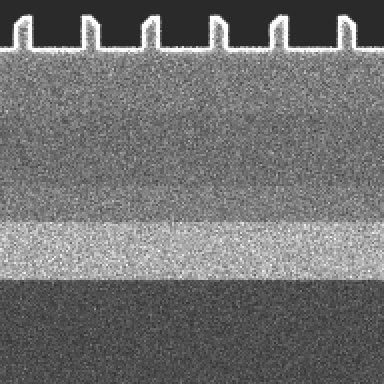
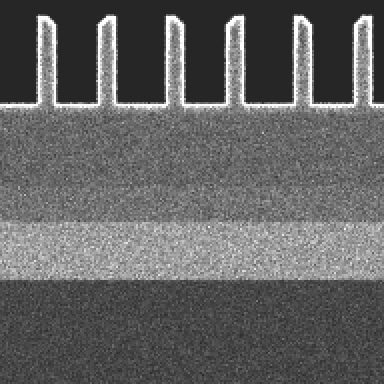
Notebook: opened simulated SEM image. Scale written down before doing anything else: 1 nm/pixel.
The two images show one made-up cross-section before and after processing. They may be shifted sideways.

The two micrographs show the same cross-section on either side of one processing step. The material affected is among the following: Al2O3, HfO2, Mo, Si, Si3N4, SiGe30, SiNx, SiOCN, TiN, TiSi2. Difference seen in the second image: TiN removed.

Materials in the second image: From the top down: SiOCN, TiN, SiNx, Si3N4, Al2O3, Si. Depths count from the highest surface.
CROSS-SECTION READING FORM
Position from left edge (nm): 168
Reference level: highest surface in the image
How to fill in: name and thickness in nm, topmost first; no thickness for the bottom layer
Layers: SiOCN 32, TiN 66, SiNx 72, Si3N4 36, Al2O3 58, Si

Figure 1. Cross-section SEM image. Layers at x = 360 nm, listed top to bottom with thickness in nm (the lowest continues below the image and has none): empty 2, SiOCN 30, TiN 66, SiNx 72, Si3N4 36, Al2O3 58, Si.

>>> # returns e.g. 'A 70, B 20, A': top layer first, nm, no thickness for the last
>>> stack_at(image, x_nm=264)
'empty 88, TiN 10, SiNx 72, Si3N4 36, Al2O3 58, Si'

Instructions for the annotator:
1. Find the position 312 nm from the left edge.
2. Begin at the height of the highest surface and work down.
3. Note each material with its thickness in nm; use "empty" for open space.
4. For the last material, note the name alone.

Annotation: empty 88, TiN 10, SiNx 72, Si3N4 36, Al2O3 58, Si